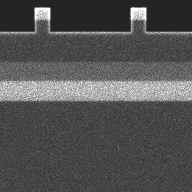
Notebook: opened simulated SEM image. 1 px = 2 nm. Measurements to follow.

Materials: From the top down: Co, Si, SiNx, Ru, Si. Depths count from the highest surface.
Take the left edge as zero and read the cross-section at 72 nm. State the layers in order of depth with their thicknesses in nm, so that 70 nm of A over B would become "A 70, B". Co 24, Si 84, SiNx 38, Ru 40, Si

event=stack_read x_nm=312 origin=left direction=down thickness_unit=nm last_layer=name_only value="empty 48, Si 60, SiNx 38, Ru 40, Si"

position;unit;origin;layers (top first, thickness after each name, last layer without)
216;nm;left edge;empty 48, Si 60, SiNx 38, Ru 40, Si